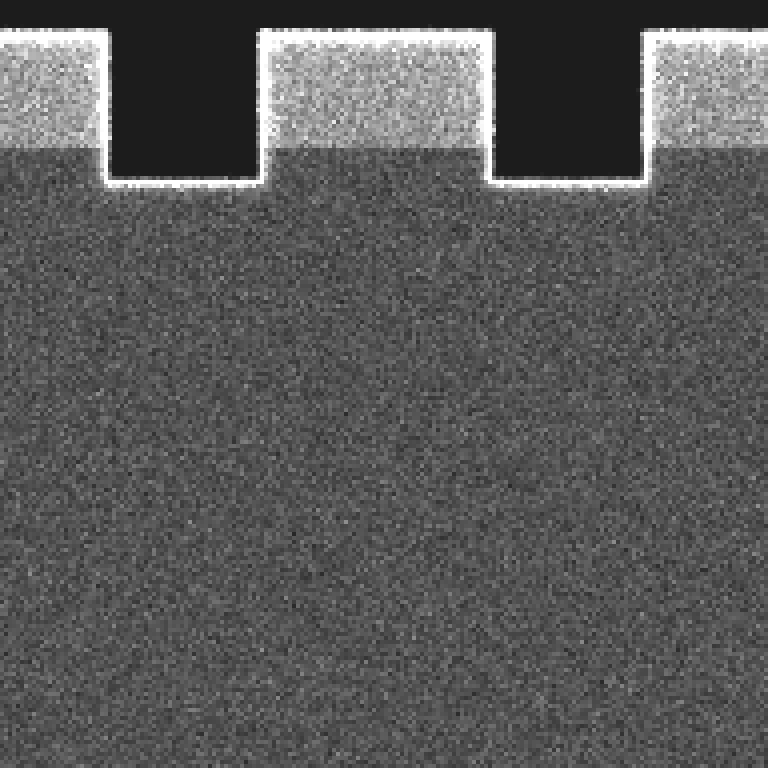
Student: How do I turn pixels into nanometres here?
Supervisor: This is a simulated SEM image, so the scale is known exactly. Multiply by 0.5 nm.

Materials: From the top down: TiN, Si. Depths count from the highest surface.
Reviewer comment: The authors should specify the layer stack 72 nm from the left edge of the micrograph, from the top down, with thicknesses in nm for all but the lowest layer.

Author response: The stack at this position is empty 74, Si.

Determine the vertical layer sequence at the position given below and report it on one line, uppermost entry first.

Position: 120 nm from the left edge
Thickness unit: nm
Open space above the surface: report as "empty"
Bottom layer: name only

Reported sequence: empty 74, Si